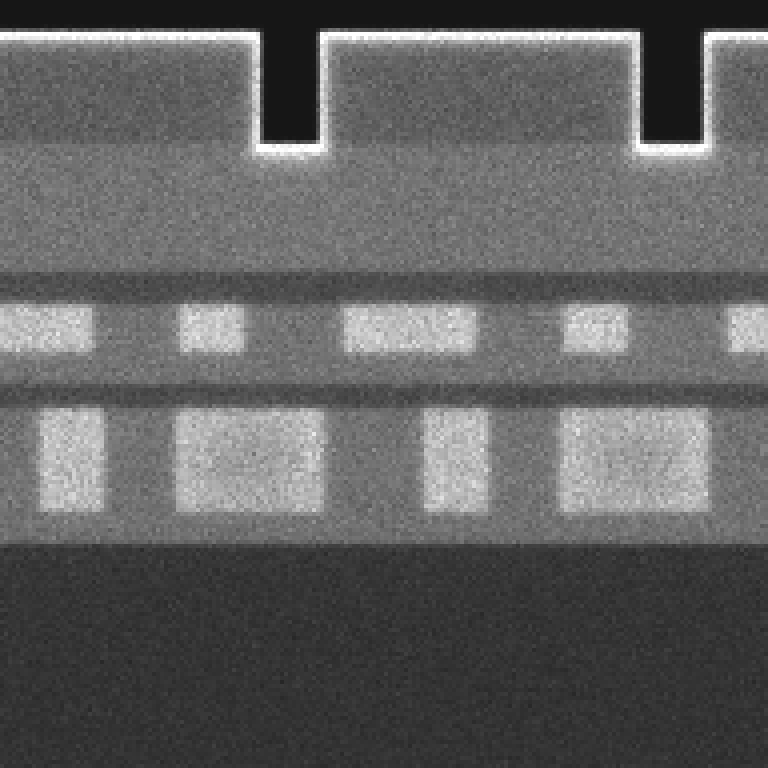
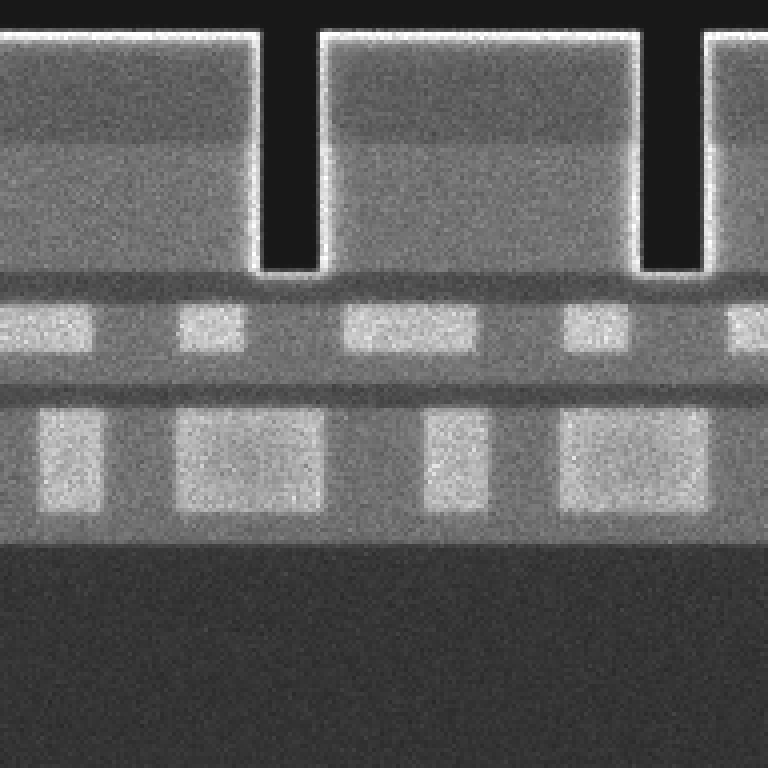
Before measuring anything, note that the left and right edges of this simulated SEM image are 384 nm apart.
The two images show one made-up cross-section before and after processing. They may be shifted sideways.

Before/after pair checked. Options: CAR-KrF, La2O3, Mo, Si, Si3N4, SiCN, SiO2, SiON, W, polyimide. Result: removed SiO2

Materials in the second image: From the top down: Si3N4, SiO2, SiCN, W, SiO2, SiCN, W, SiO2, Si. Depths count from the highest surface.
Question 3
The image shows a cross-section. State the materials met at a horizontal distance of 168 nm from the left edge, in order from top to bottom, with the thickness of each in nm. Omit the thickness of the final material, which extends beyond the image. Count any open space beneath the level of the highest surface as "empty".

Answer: Si3N4 56, SiO2 64, SiCN 16, SiO2 40, SiCN 12, SiO2 68, Si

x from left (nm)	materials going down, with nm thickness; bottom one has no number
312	Si3N4 56, SiO2 64, SiCN 16, W 24, SiO2 16, SiCN 12, W 52, SiO2 16, Si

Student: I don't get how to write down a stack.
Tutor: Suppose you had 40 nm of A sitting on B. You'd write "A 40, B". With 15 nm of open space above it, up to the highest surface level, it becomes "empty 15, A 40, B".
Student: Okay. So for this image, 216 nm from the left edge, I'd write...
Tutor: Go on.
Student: Si3N4 56, SiO2 64, SiCN 16, W 24, SiO2 16, SiCN 12, W 52, SiO2 16, Si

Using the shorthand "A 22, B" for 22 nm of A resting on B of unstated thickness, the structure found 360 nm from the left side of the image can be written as Si3N4 56, SiO2 64, SiCN 16, SiO2 40, SiCN 12, SiO2 68, Si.